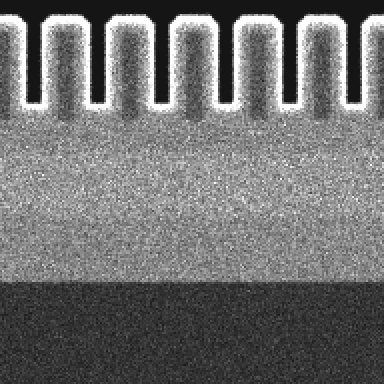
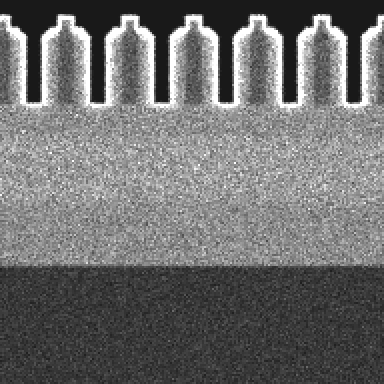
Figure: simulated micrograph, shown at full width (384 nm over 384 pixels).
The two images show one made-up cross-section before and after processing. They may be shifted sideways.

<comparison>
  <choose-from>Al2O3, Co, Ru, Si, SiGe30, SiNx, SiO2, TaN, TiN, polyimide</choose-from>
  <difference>SiO2 removed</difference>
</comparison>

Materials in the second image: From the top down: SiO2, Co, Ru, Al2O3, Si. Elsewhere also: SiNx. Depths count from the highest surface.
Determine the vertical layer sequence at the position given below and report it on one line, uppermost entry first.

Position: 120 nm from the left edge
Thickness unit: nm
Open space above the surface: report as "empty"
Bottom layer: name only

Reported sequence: empty 12, SiO2 76, Co 32, Ru 66, Al2O3 64, Si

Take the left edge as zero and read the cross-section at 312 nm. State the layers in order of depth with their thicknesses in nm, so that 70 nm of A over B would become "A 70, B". empty 12, SiO2 76, Co 32, Ru 66, Al2O3 64, Si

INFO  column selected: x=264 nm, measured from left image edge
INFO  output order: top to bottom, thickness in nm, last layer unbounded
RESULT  SiNx 88, Co 32, Ru 66, Al2O3 64, Si